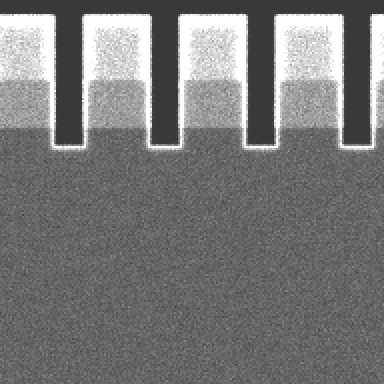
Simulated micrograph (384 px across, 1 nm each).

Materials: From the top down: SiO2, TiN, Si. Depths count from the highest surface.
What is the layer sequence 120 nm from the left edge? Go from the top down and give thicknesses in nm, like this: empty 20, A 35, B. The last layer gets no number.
SiO2 64, TiN 48, Si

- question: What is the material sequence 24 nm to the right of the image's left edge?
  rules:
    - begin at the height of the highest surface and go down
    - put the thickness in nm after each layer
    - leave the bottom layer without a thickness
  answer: SiO2 64, TiN 48, Si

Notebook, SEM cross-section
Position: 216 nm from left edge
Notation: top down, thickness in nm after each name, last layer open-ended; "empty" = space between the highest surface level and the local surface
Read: SiO2 64, TiN 48, Si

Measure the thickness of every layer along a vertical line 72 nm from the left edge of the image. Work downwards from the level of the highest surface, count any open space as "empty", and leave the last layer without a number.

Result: empty 130, Si